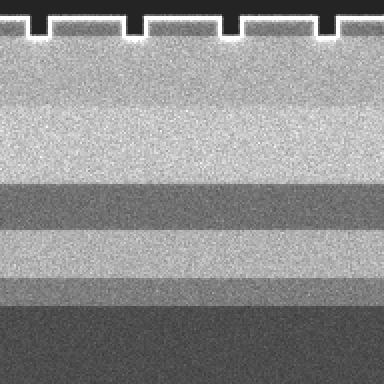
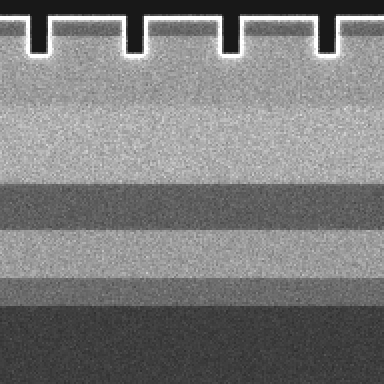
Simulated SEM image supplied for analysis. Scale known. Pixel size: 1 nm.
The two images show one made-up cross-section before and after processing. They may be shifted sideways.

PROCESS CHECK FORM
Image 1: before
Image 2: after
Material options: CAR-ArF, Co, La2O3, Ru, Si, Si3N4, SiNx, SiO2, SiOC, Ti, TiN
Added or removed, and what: removed, Co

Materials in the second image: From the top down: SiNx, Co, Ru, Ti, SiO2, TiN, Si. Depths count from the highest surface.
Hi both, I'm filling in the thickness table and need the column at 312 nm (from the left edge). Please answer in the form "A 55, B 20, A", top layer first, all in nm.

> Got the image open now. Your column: SiNx 20, Co 70, Ru 78, Ti 46, SiO2 48, TiN 28, Si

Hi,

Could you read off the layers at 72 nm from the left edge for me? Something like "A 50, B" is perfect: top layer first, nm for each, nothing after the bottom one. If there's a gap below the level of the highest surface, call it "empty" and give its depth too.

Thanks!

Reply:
SiNx 20, Co 70, Ru 78, Ti 46, SiO2 48, TiN 28, Si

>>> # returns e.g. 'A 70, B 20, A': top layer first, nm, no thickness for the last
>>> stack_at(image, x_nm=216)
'SiNx 20, Co 70, Ru 78, Ti 46, SiO2 48, TiN 28, Si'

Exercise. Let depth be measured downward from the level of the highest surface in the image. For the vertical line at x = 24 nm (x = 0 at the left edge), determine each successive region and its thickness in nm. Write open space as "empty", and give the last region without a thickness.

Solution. SiNx 20, Co 70, Ru 78, Ti 46, SiO2 48, TiN 28, Si